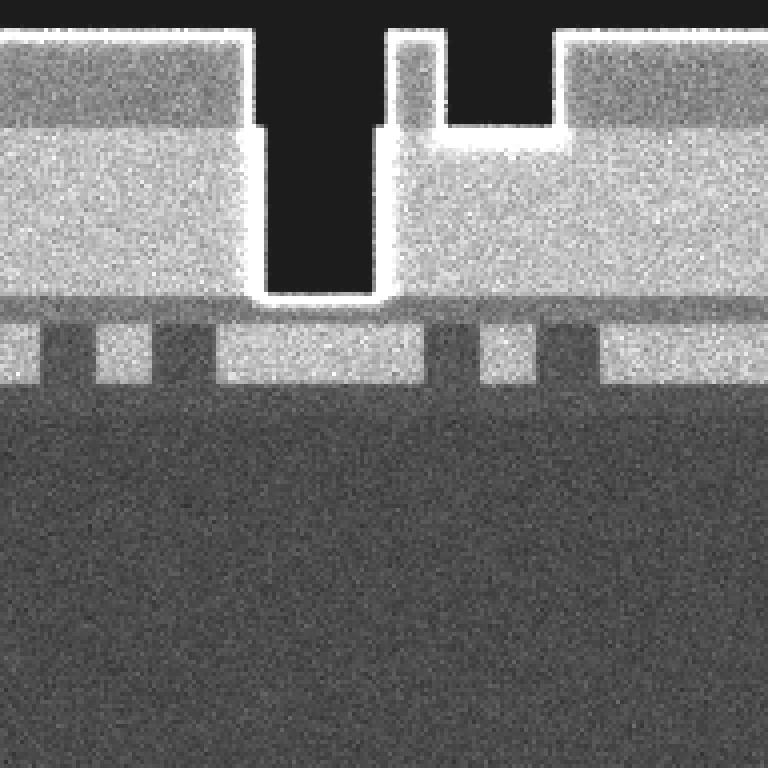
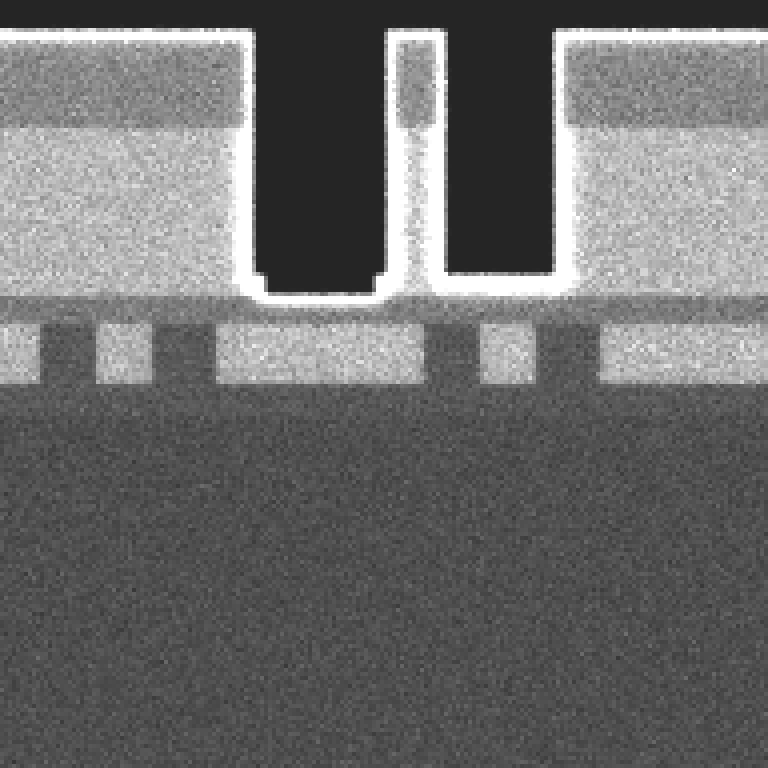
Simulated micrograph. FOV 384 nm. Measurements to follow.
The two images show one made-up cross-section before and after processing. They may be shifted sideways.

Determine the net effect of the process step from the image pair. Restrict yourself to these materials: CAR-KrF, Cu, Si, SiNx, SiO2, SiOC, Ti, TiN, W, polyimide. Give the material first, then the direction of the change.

SiO2: removed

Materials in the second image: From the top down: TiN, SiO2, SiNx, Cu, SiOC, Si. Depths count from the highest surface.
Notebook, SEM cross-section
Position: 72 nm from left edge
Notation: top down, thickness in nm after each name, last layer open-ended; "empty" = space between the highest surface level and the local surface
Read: TiN 48, SiO2 84, SiNx 14, Cu 30, SiOC 16, Si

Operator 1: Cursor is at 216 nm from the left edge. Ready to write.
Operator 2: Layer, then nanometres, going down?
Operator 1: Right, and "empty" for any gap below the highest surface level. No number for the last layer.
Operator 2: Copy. TiN 48, SiO2 84, SiNx 14, SiOC 46, Si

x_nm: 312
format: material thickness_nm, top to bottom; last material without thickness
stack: TiN 48, SiO2 84, SiNx 14, Cu 30, SiOC 16, Si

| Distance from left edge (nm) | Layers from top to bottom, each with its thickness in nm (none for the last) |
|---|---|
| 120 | TiN 48, SiO2 84, SiNx 14, Cu 30, SiOC 16, Si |